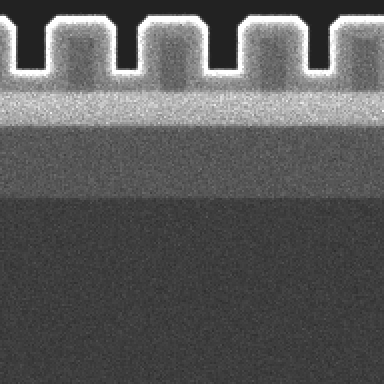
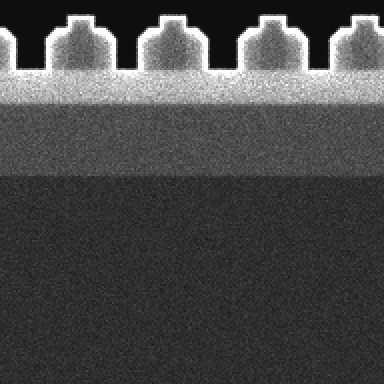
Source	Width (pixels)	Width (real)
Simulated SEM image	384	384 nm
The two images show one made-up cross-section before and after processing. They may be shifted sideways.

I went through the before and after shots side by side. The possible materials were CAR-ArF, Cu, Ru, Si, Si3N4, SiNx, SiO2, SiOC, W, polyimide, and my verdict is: removed, SiO2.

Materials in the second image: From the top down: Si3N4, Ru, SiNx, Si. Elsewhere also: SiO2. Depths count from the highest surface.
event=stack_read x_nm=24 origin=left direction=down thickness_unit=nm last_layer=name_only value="empty 54, Ru 34, SiNx 72, Si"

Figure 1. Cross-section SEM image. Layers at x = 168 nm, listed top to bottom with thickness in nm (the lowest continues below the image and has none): Si3N4 54, Ru 34, SiNx 72, Si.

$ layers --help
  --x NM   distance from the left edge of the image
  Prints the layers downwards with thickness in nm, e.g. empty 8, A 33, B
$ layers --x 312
empty 54, Ru 34, SiNx 72, Si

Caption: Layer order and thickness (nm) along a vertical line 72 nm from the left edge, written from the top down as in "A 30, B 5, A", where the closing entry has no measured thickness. Si3N4 54, Ru 34, SiNx 72, Si